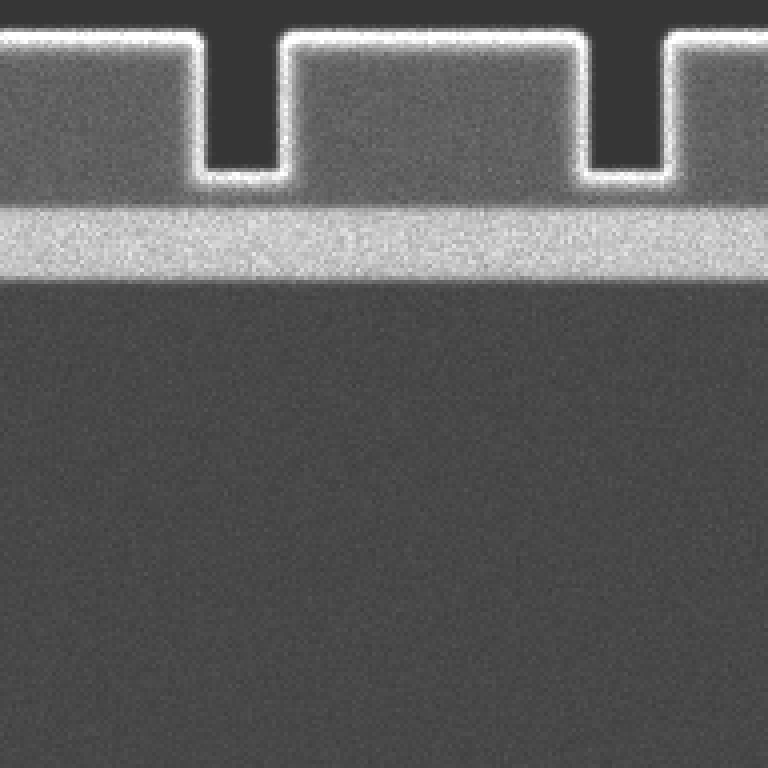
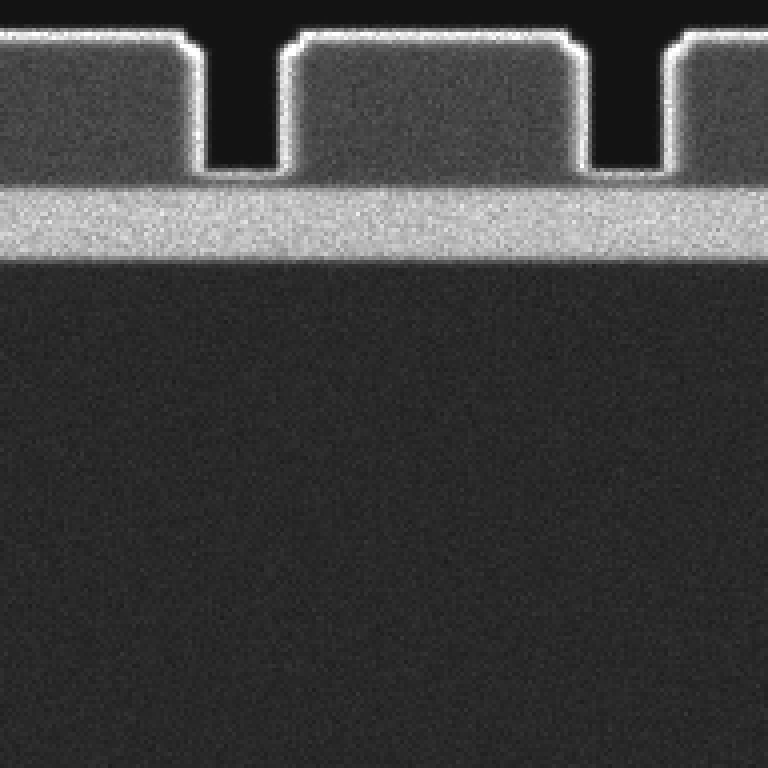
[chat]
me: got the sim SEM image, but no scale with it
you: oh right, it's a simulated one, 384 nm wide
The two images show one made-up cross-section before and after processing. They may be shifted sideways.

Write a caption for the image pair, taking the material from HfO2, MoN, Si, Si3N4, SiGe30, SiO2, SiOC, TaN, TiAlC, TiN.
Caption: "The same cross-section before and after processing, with SiO2 removed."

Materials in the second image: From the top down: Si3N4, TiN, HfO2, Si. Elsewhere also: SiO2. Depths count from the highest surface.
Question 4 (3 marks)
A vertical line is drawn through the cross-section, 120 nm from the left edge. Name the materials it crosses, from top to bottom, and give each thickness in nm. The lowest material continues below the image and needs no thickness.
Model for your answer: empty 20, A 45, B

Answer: empty 70, TiN 8, HfO2 36, Si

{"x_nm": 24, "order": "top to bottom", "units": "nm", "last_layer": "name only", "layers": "Si3N4 54, TiN 24, HfO2 36, Si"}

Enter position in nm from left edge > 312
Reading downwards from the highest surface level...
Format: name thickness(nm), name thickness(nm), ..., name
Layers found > empty 70, TiN 8, HfO2 36, Si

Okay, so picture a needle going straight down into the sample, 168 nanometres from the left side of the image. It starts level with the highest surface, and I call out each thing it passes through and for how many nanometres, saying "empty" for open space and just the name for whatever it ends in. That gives Si3N4 54, TiN 24, HfO2 36, Si